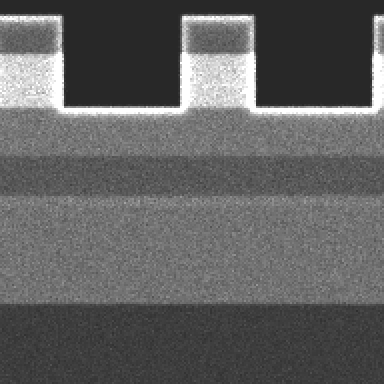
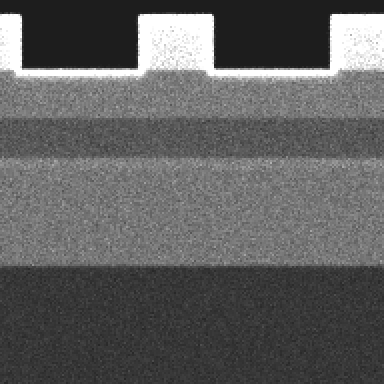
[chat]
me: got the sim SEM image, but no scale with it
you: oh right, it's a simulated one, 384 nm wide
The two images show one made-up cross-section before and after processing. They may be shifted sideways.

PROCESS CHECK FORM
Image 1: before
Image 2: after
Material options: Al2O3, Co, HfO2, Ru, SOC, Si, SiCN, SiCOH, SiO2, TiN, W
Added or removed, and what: removed, SOC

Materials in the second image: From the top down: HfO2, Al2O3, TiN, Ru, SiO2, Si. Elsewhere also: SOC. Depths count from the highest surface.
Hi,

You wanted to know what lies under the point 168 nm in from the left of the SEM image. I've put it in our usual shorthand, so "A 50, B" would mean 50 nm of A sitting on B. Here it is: HfO2 54, Al2O3 48, TiN 40, Ru 10, SiO2 98, Si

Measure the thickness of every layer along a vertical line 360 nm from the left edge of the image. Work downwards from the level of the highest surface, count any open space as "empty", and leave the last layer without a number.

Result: HfO2 54, Al2O3 48, TiN 40, Ru 10, SiO2 98, Si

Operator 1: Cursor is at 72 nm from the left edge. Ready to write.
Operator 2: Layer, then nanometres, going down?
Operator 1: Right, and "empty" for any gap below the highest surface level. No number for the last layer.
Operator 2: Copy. empty 54, Al2O3 48, TiN 40, Ru 10, SiO2 98, Si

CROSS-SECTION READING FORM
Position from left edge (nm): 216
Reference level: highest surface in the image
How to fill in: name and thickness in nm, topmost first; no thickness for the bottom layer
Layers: empty 54, Al2O3 48, TiN 40, Ru 10, SiO2 98, Si